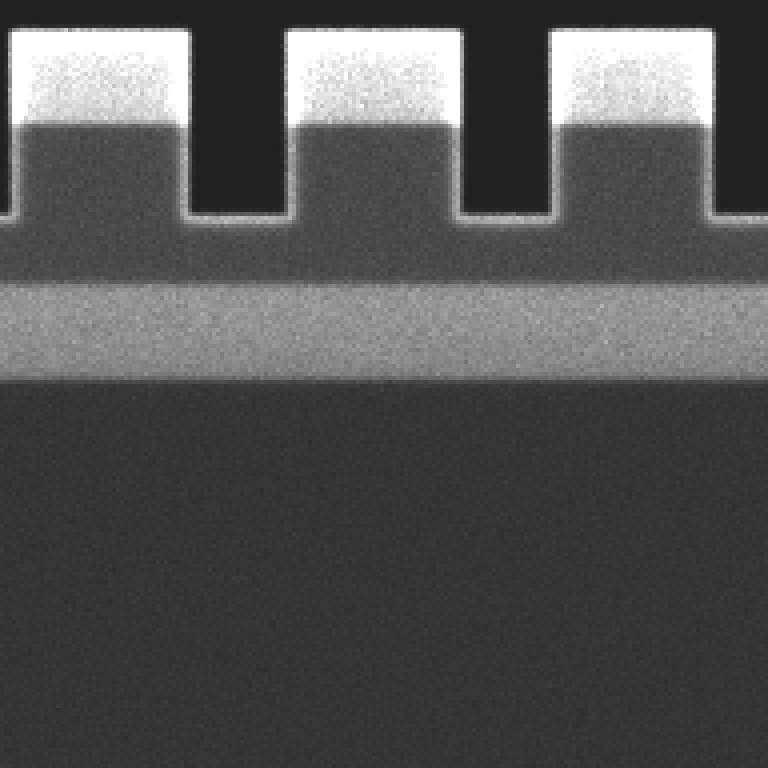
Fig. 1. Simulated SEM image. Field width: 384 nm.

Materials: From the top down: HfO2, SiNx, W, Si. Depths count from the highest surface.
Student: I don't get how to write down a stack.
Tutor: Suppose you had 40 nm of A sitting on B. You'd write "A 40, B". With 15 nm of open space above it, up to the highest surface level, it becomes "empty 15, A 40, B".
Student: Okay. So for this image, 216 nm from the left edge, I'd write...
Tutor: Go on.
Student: HfO2 46, SiNx 80, W 48, Si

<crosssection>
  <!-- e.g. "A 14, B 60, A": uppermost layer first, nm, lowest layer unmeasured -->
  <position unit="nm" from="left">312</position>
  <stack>HfO2 46, SiNx 80, W 48, Si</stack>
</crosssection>